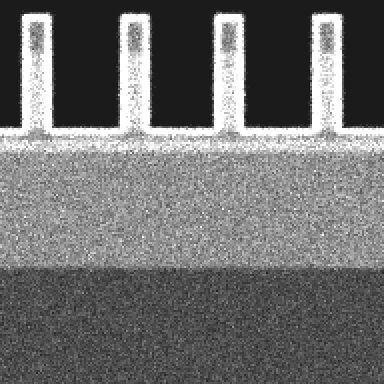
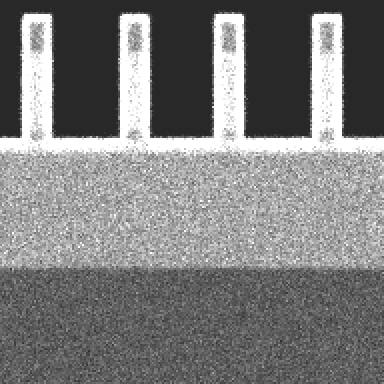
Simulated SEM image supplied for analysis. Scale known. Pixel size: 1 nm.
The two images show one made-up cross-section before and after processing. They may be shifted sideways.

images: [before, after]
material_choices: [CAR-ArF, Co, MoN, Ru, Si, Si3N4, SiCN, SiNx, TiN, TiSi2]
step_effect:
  removed: TiN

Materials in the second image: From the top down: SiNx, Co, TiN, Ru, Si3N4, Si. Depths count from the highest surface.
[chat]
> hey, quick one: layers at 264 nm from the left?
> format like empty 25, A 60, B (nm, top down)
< empty 124, Ru 12, Si3N4 116, Si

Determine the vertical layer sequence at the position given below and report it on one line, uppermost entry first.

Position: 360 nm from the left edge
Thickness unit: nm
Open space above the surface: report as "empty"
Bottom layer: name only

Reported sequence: empty 124, Ru 12, Si3N4 116, Si